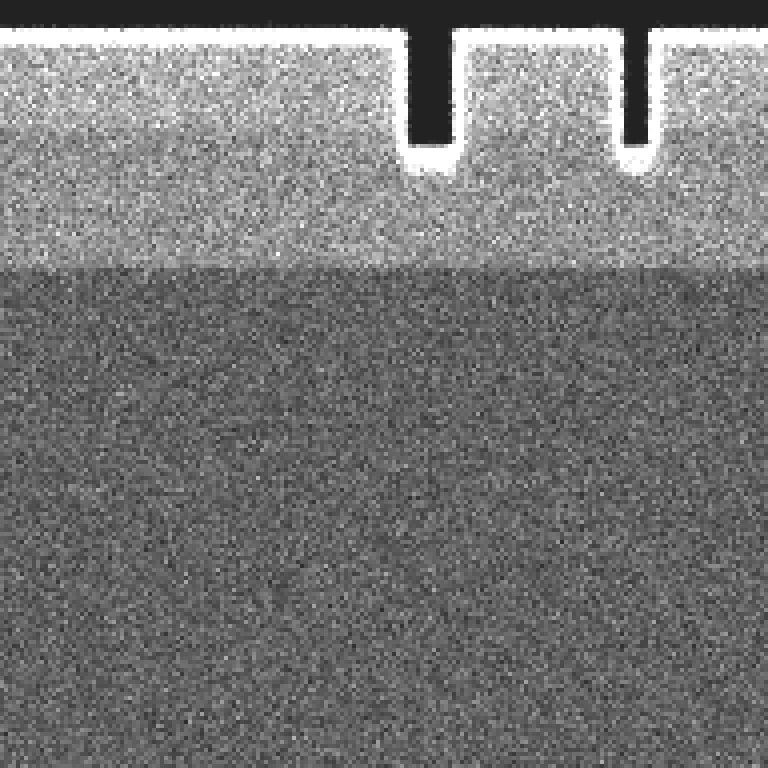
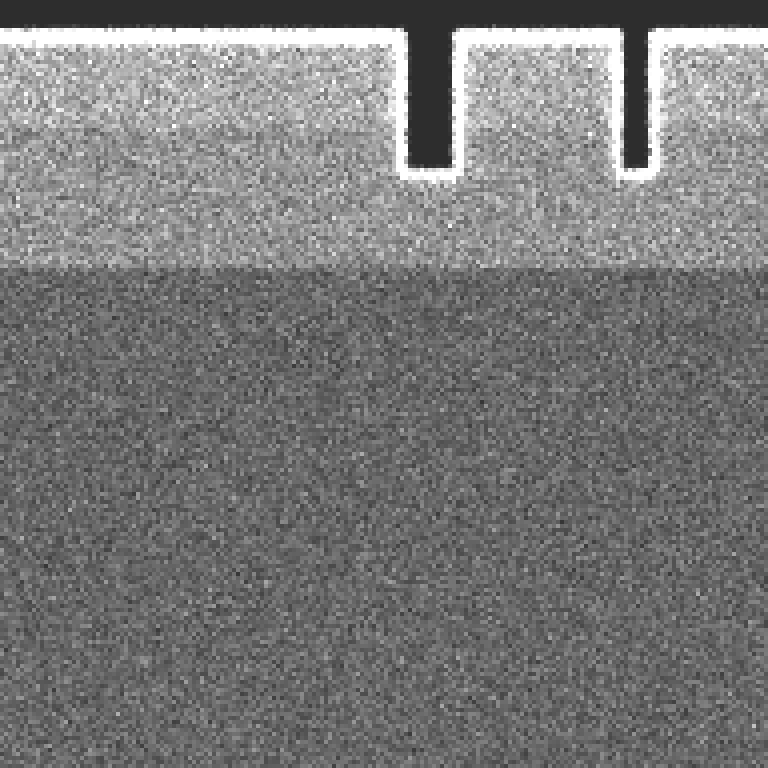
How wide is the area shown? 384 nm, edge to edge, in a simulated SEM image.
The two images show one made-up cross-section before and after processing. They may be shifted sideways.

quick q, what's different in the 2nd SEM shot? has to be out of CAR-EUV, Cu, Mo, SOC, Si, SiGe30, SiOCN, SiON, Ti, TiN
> SOC removed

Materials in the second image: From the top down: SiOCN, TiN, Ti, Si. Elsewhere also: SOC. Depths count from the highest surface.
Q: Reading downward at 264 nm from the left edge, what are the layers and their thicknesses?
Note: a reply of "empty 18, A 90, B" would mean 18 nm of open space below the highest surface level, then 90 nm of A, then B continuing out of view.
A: SiOCN 12, TiN 36, Ti 70, Si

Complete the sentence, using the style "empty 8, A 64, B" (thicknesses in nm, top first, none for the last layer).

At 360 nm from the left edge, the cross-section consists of SiOCN 12, TiN 36, Ti 70, Si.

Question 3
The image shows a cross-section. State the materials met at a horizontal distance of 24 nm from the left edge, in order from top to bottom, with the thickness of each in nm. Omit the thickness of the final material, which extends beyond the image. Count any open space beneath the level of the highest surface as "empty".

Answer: SiOCN 12, TiN 36, Ti 70, Si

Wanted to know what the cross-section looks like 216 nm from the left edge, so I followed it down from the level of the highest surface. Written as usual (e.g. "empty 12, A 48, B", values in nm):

empty 70, Ti 48, Si